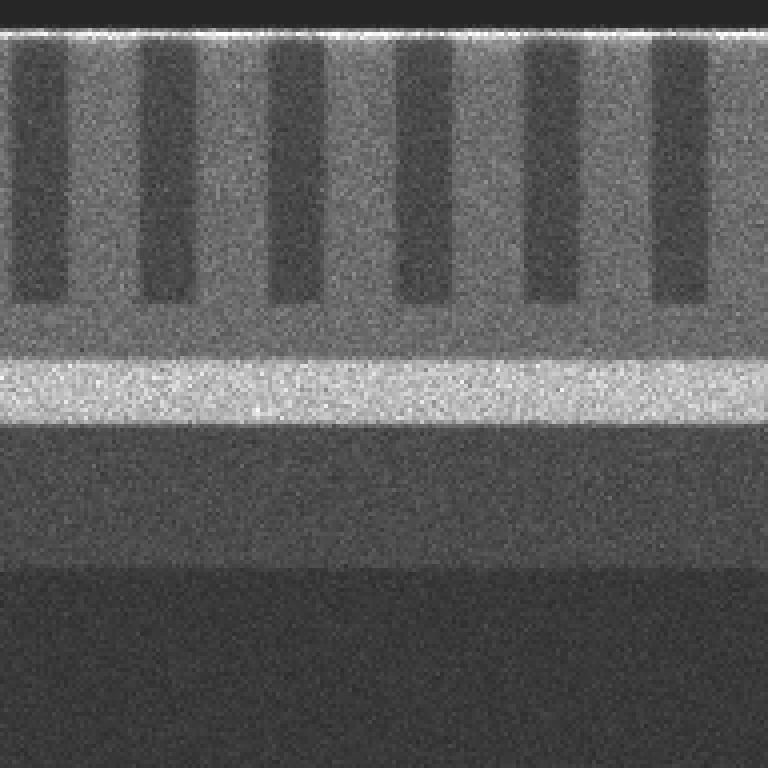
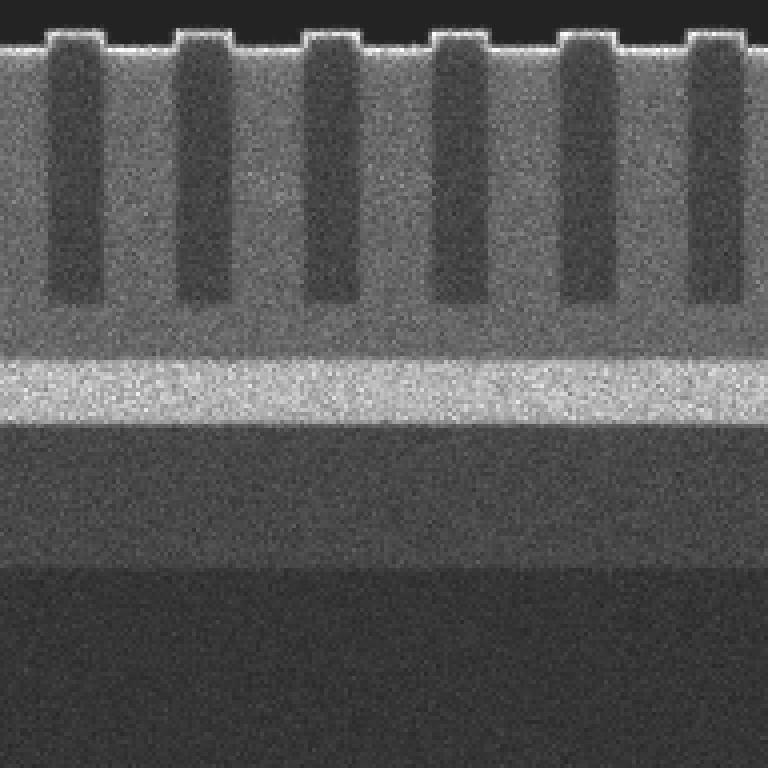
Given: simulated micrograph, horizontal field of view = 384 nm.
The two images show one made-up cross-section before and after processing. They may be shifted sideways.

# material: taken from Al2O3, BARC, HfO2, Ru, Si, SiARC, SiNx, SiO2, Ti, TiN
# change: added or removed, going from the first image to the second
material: Ru
change: removed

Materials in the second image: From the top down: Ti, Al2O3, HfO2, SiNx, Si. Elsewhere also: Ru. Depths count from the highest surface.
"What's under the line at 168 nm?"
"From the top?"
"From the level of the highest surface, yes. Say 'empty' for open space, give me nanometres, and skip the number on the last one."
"Ti 136, Al2O3 28, HfO2 32, SiNx 72, Si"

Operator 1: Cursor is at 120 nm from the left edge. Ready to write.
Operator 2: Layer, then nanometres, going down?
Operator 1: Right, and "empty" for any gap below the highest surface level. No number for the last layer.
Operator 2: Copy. empty 8, Ru 78, Al2O3 78, HfO2 32, SiNx 72, Si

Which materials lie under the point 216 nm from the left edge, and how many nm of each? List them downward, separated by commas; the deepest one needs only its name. Ti 136, Al2O3 28, HfO2 32, SiNx 72, Si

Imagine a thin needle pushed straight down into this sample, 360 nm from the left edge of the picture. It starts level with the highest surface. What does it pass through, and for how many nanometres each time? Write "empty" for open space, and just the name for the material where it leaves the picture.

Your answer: Ti 136, Al2O3 28, HfO2 32, SiNx 72, Si